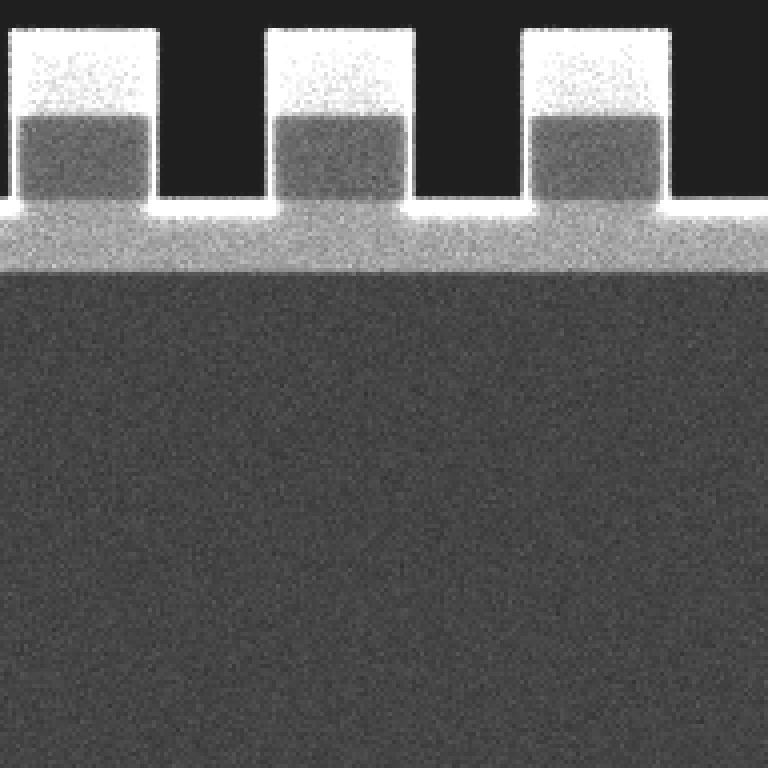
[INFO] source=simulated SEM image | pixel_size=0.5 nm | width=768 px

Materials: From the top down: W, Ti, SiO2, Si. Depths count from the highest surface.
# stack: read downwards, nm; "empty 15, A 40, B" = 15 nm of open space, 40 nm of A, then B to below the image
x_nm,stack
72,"W 42, Ti 42, SiO2 36, Si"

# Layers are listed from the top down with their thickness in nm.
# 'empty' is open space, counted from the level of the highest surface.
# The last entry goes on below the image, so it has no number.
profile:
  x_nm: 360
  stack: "empty 84, SiO2 36, Si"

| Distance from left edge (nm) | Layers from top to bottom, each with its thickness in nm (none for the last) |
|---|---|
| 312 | W 42, Ti 42, SiO2 36, Si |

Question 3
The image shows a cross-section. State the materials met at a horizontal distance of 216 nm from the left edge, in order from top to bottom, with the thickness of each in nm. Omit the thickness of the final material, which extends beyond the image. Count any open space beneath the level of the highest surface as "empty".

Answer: empty 84, SiO2 36, Si